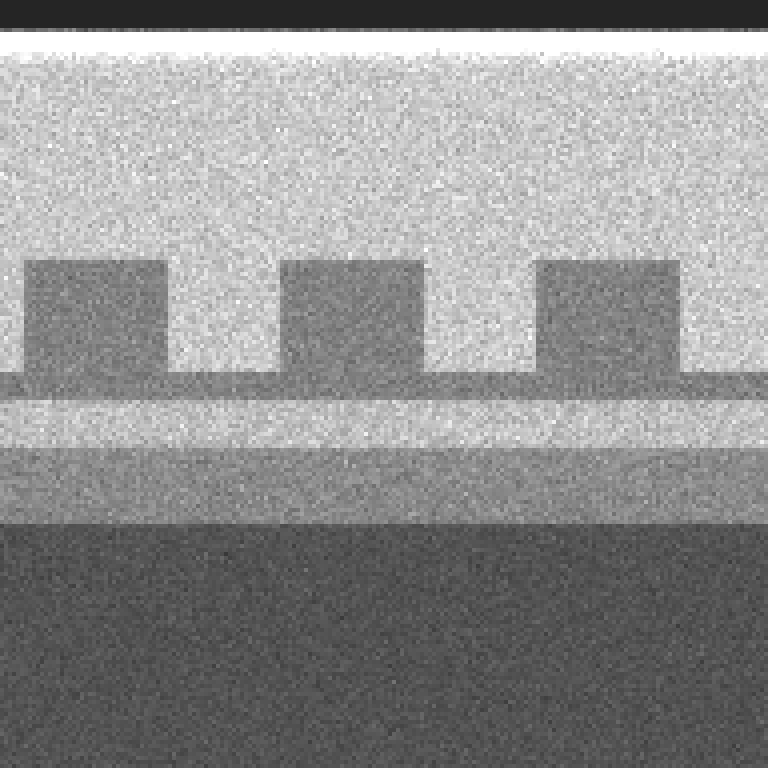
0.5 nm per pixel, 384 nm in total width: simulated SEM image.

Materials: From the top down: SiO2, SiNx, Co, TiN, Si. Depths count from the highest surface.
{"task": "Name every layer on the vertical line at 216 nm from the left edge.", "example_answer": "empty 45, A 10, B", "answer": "SiO2 170, SiNx 14, Co 24, TiN 38, Si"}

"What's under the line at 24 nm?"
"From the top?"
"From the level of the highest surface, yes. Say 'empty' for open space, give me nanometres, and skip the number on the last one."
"SiO2 114, SiNx 70, Co 24, TiN 38, Si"